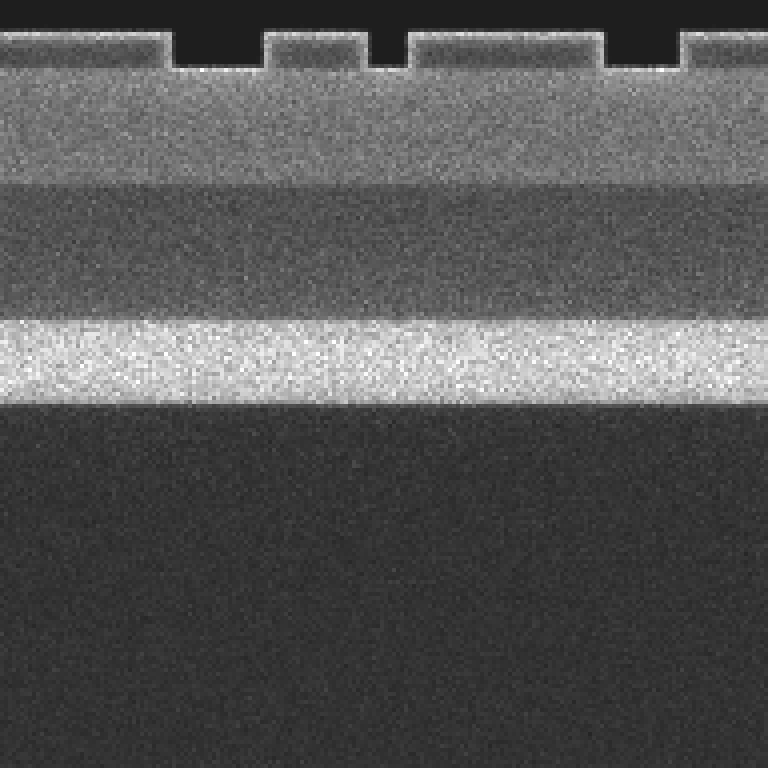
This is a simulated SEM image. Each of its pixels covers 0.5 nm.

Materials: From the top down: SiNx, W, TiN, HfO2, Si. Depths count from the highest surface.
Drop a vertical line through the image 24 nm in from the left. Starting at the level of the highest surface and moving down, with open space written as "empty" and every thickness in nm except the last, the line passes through SiNx 18, W 58, TiN 68, HfO2 42, Si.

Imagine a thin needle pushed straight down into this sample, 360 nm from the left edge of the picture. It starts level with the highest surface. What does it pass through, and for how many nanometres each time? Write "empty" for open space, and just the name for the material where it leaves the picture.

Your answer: SiNx 18, W 58, TiN 68, HfO2 42, Si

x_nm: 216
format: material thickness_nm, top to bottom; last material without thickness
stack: SiNx 18, W 58, TiN 68, HfO2 42, Si